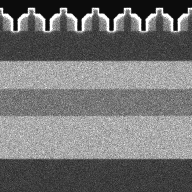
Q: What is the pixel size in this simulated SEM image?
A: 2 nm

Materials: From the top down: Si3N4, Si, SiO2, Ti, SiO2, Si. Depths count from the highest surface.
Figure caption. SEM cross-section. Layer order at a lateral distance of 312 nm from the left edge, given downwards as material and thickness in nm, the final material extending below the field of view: Si 106, SiO2 56, Ti 54, SiO2 86, Si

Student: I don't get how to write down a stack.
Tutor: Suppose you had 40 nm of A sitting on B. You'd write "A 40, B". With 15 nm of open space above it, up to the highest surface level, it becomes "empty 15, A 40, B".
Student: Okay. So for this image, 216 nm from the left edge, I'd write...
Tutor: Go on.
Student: empty 22, Si3N4 24, Si 60, SiO2 56, Ti 54, SiO2 86, Si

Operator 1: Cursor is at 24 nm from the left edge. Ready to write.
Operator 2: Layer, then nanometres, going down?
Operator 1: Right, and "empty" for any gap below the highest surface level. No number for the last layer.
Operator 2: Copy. empty 22, Si3N4 24, Si 60, SiO2 56, Ti 54, SiO2 86, Si